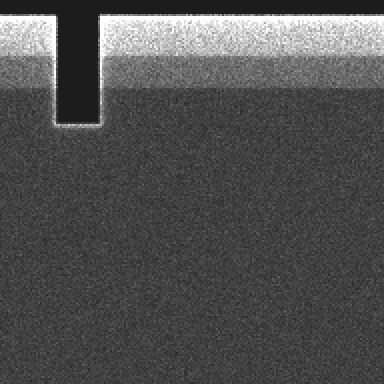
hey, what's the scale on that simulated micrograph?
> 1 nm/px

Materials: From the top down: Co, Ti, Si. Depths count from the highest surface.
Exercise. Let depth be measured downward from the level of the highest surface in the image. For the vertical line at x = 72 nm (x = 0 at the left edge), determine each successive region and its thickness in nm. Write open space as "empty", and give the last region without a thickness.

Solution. empty 108, Si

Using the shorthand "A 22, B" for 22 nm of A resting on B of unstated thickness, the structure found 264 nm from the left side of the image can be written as Co 40, Ti 32, Si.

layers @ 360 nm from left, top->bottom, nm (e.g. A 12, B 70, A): Co 40, Ti 32, Si